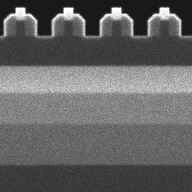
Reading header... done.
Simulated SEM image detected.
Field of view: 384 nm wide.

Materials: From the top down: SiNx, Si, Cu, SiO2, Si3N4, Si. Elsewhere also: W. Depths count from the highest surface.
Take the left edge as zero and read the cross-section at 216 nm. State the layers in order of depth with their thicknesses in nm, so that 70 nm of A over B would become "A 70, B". empty 12, SiNx 44, Si 60, Cu 54, SiO2 62, Si3N4 82, Si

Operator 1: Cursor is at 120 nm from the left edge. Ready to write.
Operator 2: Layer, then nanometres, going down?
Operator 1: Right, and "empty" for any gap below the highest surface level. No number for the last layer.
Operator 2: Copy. empty 12, SiNx 44, Si 60, Cu 54, SiO2 62, Si3N4 82, Si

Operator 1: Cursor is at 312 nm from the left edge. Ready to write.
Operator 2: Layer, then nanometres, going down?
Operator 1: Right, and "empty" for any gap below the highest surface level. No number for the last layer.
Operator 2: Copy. empty 12, SiNx 44, Si 60, Cu 54, SiO2 62, Si3N4 82, Si